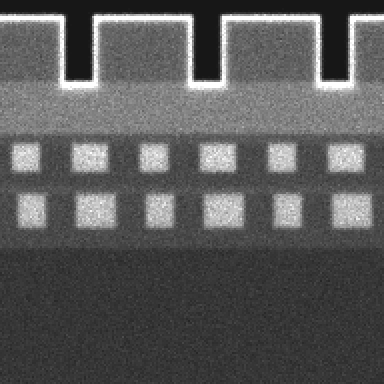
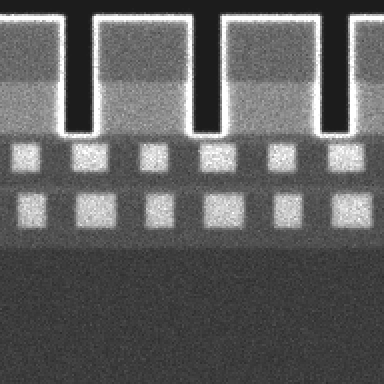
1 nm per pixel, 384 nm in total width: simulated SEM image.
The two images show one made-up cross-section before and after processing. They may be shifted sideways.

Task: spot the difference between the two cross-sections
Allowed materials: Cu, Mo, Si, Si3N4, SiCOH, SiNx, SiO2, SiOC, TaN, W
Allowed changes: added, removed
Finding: removed SiO2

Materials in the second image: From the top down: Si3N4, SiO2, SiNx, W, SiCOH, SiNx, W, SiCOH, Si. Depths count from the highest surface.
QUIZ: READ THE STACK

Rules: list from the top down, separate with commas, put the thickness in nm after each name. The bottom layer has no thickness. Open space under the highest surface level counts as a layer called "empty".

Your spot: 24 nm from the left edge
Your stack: Si3N4 66, SiO2 52, SiNx 10, W 28, SiCOH 14, SiNx 8, W 34, SiCOH 20, Si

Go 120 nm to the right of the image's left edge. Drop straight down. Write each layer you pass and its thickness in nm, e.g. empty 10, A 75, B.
Si3N4 66, SiO2 52, SiNx 10, SiCOH 42, SiNx 8, SiCOH 54, Si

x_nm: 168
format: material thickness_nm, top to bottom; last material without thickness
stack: Si3N4 66, SiO2 52, SiNx 10, SiCOH 42, SiNx 8, W 34, SiCOH 20, Si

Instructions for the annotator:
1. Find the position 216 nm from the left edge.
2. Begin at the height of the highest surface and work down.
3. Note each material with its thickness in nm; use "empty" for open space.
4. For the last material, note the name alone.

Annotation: empty 118, SiNx 10, W 28, SiCOH 14, SiNx 8, W 34, SiCOH 20, Si